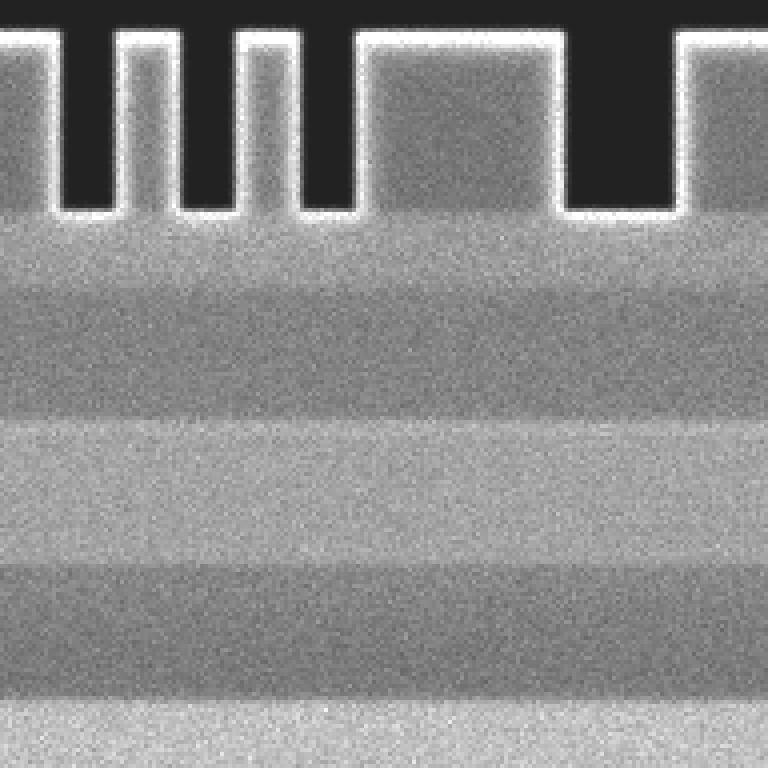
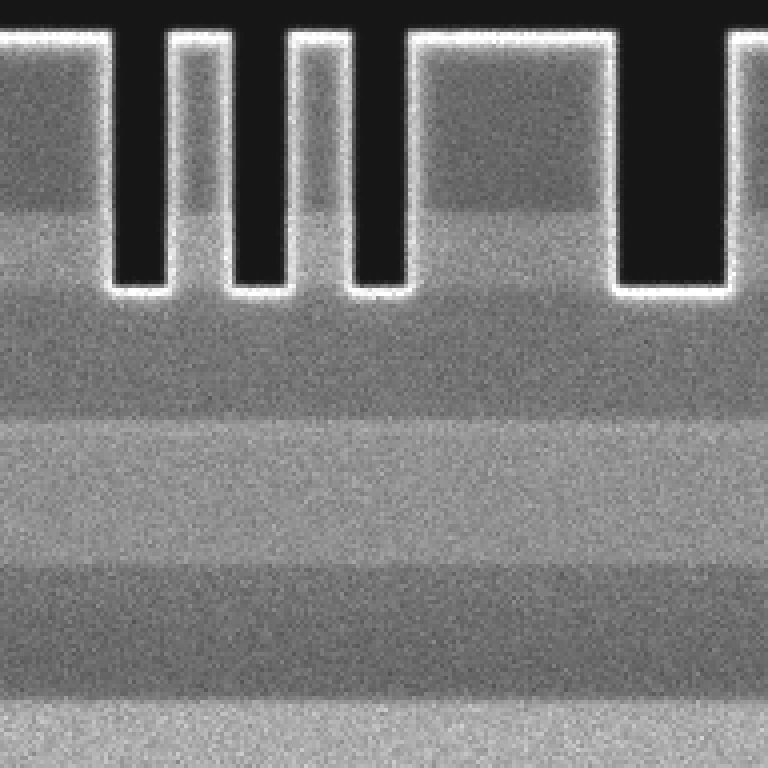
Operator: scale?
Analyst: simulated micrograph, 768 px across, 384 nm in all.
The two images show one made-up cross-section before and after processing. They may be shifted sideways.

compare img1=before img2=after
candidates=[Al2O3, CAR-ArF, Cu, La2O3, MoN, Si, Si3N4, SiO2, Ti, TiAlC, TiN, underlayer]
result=removed:TiN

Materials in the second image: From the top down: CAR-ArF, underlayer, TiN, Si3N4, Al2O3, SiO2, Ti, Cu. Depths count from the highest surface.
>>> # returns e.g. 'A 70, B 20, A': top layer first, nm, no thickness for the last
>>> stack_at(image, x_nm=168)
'CAR-ArF 72, underlayer 18, TiN 38, Si3N4 66, Al2O3 8, SiO2 64, Ti 68, Cu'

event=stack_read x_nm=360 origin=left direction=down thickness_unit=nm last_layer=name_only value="empty 128, Si3N4 66, Al2O3 8, SiO2 64, Ti 68, Cu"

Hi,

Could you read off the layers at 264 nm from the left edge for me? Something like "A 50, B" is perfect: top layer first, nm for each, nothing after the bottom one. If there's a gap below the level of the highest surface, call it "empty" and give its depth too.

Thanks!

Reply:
CAR-ArF 72, underlayer 18, TiN 38, Si3N4 66, Al2O3 8, SiO2 64, Ti 68, Cu